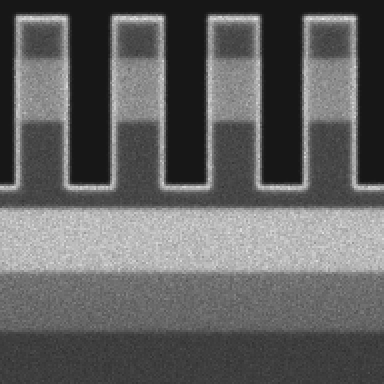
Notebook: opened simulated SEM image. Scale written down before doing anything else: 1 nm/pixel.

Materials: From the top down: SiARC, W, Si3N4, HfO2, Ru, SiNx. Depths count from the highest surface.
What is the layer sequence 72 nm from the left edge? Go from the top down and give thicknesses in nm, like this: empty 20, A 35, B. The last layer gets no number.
empty 170, Si3N4 22, HfO2 64, Ru 60, SiNx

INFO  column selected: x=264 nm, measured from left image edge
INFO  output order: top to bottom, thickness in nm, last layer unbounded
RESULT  empty 170, Si3N4 22, HfO2 64, Ru 60, SiNx